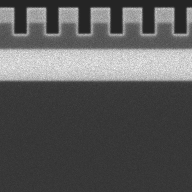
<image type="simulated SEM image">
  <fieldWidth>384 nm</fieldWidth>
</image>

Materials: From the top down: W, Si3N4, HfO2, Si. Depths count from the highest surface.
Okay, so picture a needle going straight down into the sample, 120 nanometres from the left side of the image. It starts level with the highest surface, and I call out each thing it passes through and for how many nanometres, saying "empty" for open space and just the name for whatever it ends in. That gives W 30, Si3N4 52, HfO2 64, Si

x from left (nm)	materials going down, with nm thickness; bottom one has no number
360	empty 52, Si3N4 30, HfO2 64, Si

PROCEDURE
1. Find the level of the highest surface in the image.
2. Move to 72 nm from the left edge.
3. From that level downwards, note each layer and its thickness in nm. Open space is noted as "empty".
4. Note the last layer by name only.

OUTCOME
W 30, Si3N4 52, HfO2 64, Si